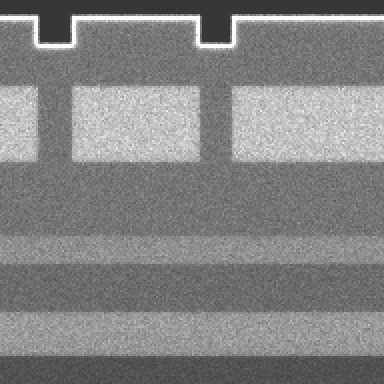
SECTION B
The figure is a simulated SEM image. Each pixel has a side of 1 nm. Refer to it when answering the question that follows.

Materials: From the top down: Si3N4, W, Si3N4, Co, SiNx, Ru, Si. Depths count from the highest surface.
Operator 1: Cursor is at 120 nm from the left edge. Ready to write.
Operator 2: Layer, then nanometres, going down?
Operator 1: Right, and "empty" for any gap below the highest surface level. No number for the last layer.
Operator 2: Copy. Si3N4 70, W 76, Si3N4 74, Co 28, SiNx 48, Ru 44, Si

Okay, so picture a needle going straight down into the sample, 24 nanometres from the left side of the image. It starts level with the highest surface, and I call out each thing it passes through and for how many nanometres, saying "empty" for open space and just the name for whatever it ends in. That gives Si3N4 70, W 76, Si3N4 74, Co 28, SiNx 48, Ru 44, Si